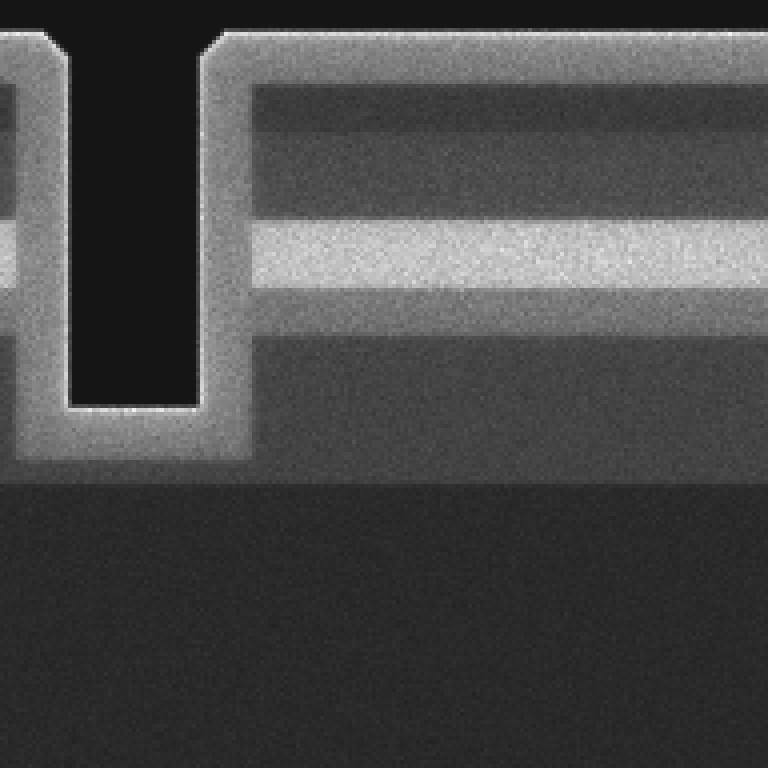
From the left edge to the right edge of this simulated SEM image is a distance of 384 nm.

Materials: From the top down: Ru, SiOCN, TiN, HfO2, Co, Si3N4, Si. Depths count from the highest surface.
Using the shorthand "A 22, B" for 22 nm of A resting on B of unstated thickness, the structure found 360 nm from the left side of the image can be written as Ru 26, SiOCN 24, TiN 44, HfO2 34, Co 24, Si3N4 74, Si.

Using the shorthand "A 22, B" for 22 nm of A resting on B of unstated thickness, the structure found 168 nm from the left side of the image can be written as Ru 26, SiOCN 24, TiN 44, HfO2 34, Co 24, Si3N4 74, Si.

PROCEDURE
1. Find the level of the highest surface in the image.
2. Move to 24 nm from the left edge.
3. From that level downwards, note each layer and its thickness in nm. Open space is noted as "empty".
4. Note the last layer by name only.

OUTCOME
empty 4, Ru 210, Si3N4 12, Si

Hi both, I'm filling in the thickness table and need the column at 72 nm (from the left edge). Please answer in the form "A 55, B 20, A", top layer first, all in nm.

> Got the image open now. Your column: empty 188, Ru 26, Si3N4 12, Si